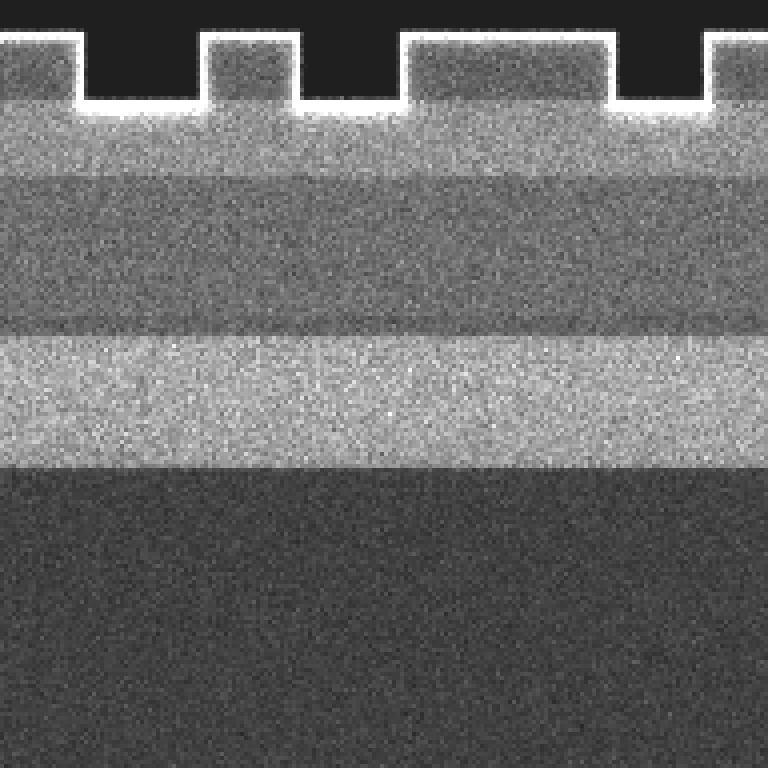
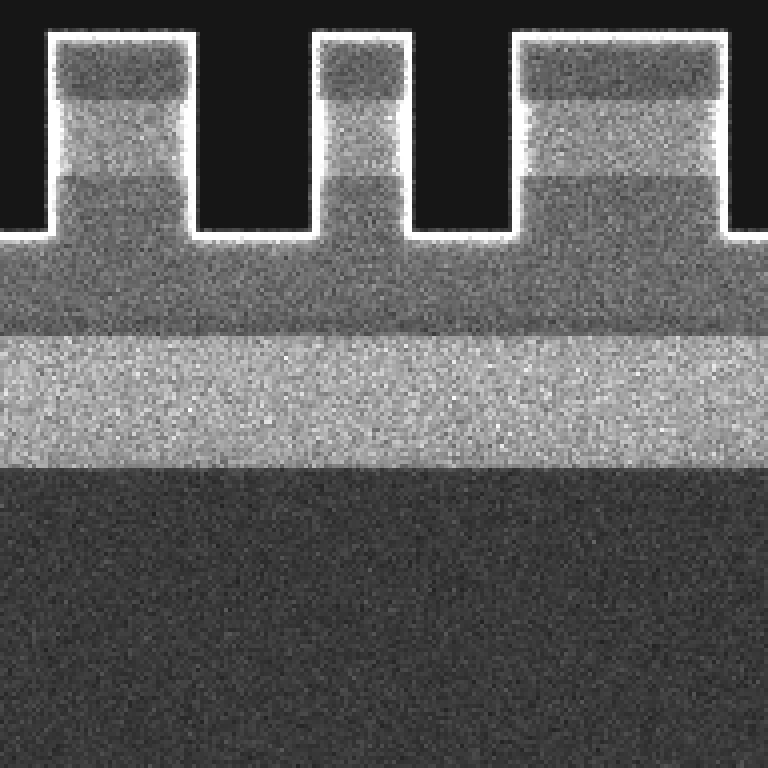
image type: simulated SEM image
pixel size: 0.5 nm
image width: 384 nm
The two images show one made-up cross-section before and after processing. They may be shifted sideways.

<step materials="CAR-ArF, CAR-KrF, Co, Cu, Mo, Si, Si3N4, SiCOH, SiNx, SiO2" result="removed Si3N4 and SiO2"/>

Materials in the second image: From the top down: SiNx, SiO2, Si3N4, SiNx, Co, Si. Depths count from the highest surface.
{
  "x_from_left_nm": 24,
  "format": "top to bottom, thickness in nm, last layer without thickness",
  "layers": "SiNx 34, SiO2 38, Si3N4 70, SiNx 10, Co 66, Si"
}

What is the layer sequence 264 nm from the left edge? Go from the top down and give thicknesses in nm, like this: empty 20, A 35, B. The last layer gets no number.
SiNx 34, SiO2 38, Si3N4 70, SiNx 10, Co 66, Si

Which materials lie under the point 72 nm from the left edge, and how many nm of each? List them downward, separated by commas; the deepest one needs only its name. SiNx 34, SiO2 38, Si3N4 70, SiNx 10, Co 66, Si